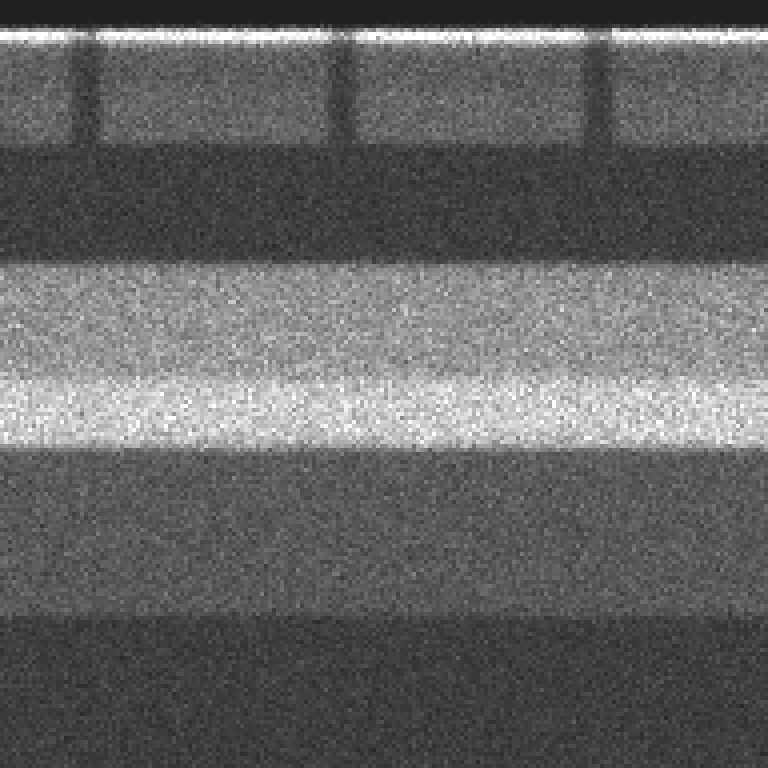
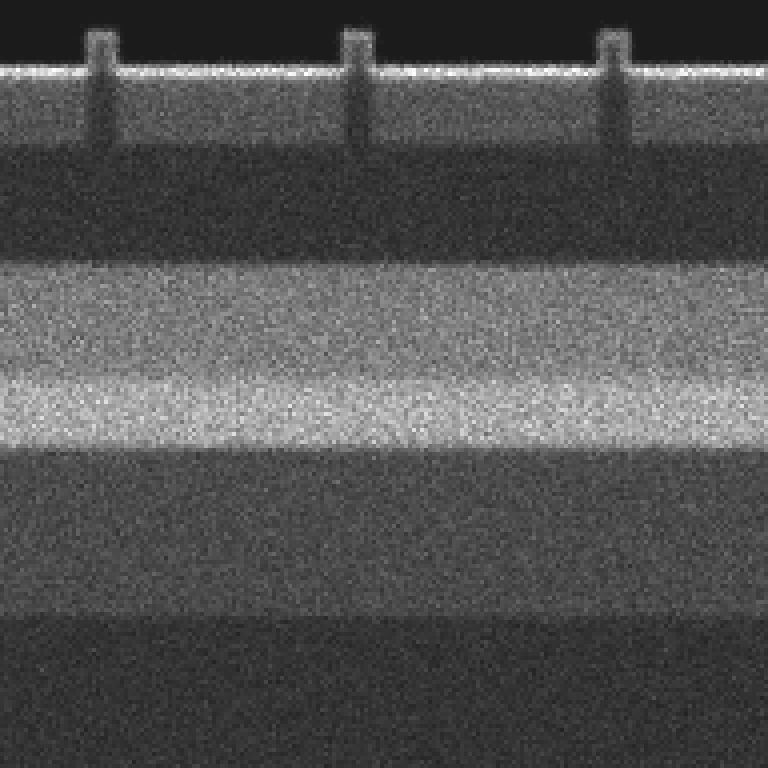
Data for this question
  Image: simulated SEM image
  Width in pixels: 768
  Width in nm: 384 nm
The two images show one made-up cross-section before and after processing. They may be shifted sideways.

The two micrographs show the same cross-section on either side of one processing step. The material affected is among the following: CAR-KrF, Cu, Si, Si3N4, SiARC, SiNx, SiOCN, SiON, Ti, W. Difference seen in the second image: SiNx removed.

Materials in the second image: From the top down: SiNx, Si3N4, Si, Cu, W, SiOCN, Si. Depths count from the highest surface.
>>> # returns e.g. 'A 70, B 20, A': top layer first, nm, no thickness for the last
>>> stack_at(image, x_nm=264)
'empty 18, SiNx 10, Si3N4 28, Si 60, Cu 58, W 34, SiOCN 84, Si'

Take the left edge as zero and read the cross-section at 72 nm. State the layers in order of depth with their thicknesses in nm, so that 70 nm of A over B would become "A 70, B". empty 18, SiNx 10, Si3N4 28, Si 60, Cu 58, W 34, SiOCN 84, Si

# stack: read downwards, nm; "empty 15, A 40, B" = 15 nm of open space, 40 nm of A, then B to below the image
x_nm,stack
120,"empty 18, SiNx 10, Si3N4 28, Si 60, Cu 58, W 34, SiOCN 84, Si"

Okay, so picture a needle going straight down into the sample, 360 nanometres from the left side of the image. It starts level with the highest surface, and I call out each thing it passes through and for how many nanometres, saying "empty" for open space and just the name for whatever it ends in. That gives empty 18, SiNx 10, Si3N4 28, Si 60, Cu 58, W 34, SiOCN 84, Si